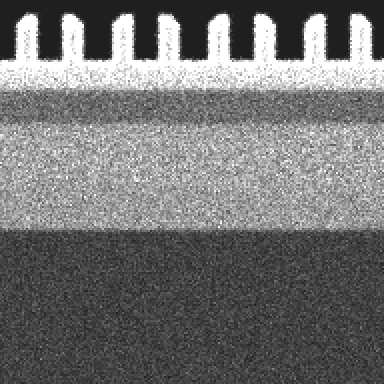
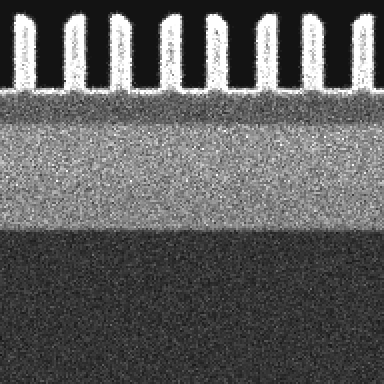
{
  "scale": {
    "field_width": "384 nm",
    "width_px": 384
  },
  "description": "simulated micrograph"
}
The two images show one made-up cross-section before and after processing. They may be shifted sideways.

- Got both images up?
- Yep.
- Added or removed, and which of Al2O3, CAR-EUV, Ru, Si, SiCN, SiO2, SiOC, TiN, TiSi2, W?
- removed, W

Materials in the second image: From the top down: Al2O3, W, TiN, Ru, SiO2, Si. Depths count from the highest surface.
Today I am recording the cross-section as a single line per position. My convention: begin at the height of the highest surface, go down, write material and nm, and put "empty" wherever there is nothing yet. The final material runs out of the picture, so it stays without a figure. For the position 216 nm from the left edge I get Al2O3 46, W 28, TiN 34, Ru 62, SiO2 44, Si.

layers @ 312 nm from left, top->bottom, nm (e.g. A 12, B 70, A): Al2O3 46, W 28, TiN 34, Ru 62, SiO2 44, Si